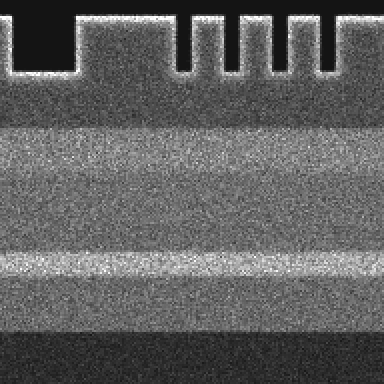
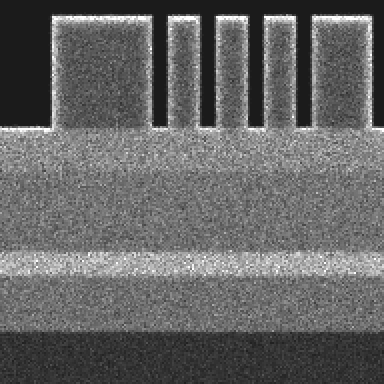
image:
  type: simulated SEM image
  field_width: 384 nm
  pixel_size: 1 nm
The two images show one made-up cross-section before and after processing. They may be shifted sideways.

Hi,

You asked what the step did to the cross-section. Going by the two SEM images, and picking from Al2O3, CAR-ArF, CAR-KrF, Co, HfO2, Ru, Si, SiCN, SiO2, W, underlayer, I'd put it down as underlayer, removed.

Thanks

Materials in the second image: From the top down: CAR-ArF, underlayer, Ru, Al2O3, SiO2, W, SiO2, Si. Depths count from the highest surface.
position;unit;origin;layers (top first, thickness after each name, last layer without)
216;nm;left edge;CAR-ArF 56, underlayer 56, Ru 44, Al2O3 54, SiO2 26, W 24, SiO2 56, Si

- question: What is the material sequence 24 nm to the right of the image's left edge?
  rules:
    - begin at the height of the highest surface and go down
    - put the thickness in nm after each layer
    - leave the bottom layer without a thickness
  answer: empty 112, Ru 44, Al2O3 54, SiO2 26, W 24, SiO2 56, Si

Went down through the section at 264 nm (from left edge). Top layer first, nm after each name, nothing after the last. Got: CAR-ArF 56, underlayer 56, Ru 44, Al2O3 54, SiO2 26, W 24, SiO2 56, Si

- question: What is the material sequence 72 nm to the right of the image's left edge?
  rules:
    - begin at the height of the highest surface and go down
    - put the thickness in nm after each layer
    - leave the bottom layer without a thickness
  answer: CAR-ArF 56, underlayer 56, Ru 44, Al2O3 54, SiO2 26, W 24, SiO2 56, Si